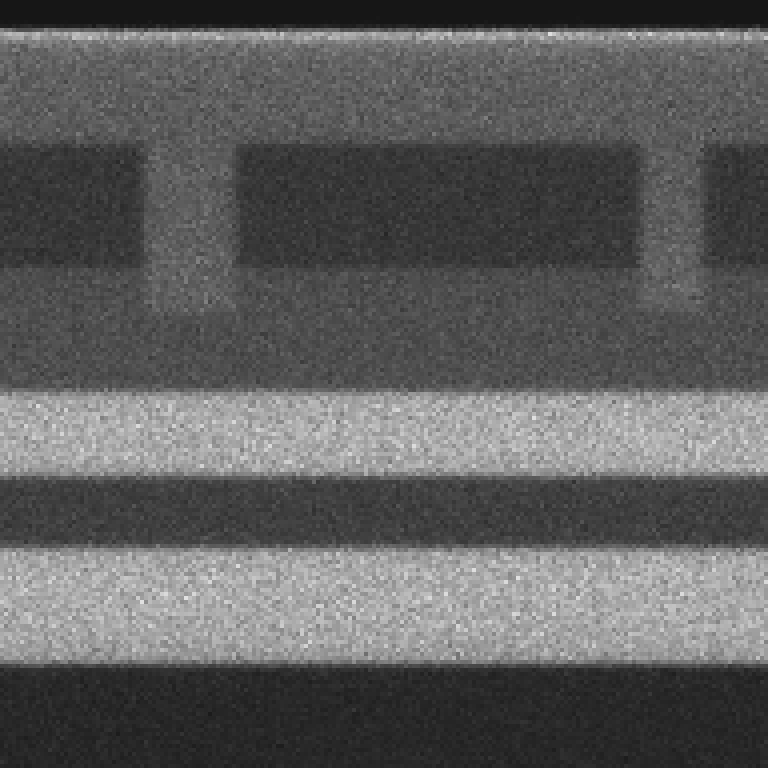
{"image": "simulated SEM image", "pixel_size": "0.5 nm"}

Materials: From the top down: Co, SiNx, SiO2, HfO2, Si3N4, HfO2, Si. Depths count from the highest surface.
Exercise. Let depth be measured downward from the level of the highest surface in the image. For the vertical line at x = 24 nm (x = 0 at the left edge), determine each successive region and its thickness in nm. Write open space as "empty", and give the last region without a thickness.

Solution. Co 56, SiNx 62, SiO2 62, HfO2 42, Si3N4 36, HfO2 58, Si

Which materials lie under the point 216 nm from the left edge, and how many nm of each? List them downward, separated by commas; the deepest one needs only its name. Co 56, SiNx 62, SiO2 62, HfO2 42, Si3N4 36, HfO2 58, Si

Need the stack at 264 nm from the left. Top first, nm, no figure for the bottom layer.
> Co 56, SiNx 62, SiO2 62, HfO2 42, Si3N4 36, HfO2 58, Si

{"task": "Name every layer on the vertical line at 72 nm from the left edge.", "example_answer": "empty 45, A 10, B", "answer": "Co 140, SiO2 40, HfO2 42, Si3N4 36, HfO2 58, Si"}